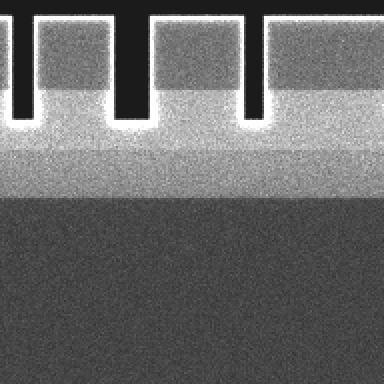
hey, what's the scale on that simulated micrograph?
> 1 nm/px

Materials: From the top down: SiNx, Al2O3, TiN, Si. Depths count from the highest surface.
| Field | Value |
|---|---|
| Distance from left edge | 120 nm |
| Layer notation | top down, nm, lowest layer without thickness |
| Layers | empty 104, Al2O3 30, TiN 48, Si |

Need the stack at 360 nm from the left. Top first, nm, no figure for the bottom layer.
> SiNx 74, Al2O3 60, TiN 48, Si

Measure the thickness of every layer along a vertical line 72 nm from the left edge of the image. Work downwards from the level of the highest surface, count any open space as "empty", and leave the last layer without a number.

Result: SiNx 74, Al2O3 60, TiN 48, Si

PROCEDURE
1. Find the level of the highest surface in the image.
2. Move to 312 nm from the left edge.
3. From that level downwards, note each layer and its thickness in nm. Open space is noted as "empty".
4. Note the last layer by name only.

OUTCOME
SiNx 74, Al2O3 60, TiN 48, Si